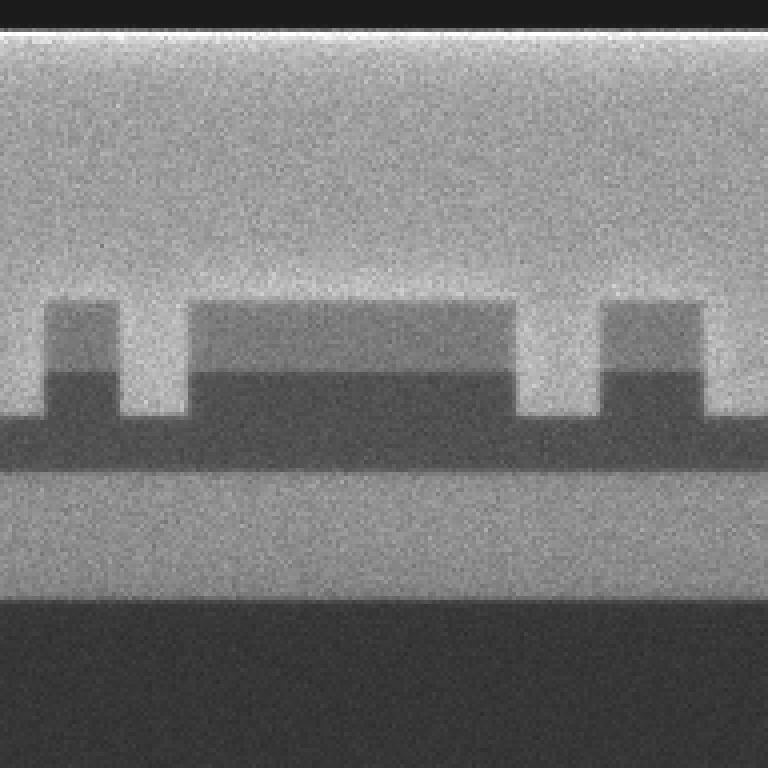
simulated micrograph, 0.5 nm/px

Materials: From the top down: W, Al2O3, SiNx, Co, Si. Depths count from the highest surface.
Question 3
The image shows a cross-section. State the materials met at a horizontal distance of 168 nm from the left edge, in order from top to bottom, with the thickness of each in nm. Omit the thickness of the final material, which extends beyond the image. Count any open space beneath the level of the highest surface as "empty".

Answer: W 134, Al2O3 36, SiNx 50, Co 64, Si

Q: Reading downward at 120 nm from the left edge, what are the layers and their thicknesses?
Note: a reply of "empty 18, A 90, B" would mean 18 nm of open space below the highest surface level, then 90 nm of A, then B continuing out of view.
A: W 134, Al2O3 36, SiNx 50, Co 64, Si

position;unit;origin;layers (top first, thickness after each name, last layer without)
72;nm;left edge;W 192, SiNx 28, Co 64, Si